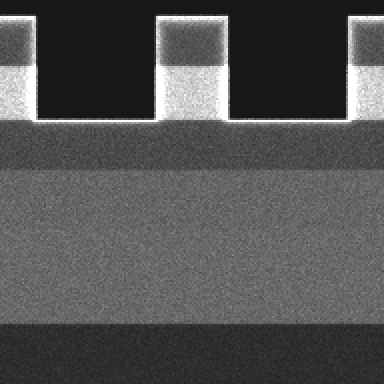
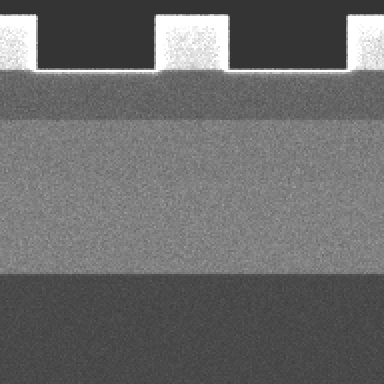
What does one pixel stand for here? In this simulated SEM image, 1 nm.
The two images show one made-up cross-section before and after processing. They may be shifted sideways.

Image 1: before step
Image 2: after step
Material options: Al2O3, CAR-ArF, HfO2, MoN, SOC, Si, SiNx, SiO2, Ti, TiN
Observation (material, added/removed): SOC, removed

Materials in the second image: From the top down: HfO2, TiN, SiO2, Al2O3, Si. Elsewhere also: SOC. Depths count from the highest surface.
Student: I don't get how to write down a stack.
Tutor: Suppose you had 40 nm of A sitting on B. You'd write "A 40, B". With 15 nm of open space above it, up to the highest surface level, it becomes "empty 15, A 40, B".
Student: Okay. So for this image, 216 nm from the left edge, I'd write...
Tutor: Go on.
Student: HfO2 54, TiN 50, SiO2 60, Al2O3 94, Si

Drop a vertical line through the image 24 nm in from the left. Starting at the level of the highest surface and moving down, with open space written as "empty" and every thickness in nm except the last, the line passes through HfO2 54, TiN 50, SiO2 60, Al2O3 94, Si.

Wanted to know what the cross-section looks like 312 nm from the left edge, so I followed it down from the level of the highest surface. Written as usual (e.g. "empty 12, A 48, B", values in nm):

empty 54, TiN 50, SiO2 60, Al2O3 94, Si